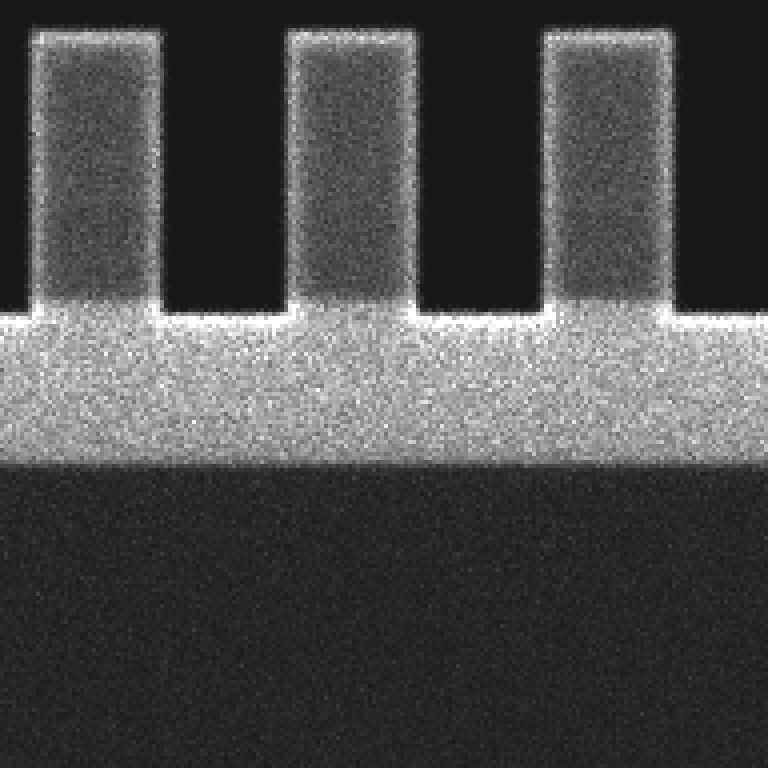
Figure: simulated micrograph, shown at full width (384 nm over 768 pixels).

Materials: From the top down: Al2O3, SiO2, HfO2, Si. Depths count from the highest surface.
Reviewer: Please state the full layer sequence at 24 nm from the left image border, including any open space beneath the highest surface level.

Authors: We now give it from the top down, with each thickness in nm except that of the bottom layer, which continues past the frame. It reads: Al2O3 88, SiO2 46, HfO2 82, Si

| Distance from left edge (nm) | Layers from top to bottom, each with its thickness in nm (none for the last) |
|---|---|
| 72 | Al2O3 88, SiO2 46, HfO2 82, Si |